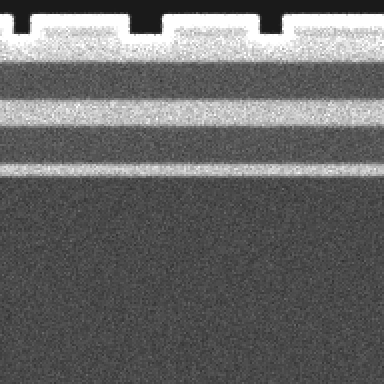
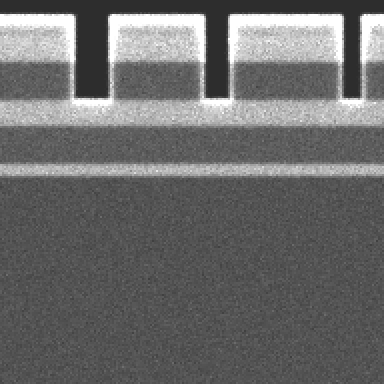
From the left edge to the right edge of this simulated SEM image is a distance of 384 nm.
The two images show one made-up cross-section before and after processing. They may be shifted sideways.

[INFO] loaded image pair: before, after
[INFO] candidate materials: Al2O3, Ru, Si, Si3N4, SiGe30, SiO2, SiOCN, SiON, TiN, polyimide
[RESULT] removed Ru and SiGe30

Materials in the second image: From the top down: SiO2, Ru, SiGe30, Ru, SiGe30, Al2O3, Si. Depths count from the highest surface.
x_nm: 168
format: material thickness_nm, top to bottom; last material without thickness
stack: SiO2 20, Ru 26, SiGe30 38, Ru 26, SiGe30 38, Al2O3 12, Si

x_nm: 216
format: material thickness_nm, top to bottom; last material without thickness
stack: empty 84, Ru 26, SiGe30 38, Al2O3 12, Si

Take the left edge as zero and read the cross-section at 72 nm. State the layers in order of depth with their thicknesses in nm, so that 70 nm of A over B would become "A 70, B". SiO2 20, Ru 26, SiGe30 38, Ru 26, SiGe30 38, Al2O3 12, Si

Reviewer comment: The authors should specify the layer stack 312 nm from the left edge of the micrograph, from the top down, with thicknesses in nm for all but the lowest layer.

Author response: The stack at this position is SiO2 20, Ru 26, SiGe30 38, Ru 26, SiGe30 38, Al2O3 12, Si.